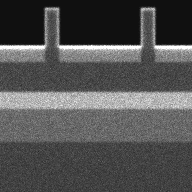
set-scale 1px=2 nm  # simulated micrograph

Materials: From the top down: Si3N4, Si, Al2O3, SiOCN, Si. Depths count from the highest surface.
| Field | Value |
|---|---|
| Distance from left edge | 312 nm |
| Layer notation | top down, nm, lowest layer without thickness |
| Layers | empty 76, Si3N4 32, Si 60, Al2O3 34, SiOCN 66, Si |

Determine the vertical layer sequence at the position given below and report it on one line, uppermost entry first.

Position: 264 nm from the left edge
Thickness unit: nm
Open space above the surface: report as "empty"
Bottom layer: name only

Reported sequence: empty 76, Si3N4 32, Si 60, Al2O3 34, SiOCN 66, Si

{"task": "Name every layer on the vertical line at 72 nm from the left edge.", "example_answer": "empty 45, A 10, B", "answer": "empty 76, Si3N4 32, Si 60, Al2O3 34, SiOCN 66, Si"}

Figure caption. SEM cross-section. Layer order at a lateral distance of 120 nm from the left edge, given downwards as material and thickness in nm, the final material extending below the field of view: empty 76, Si3N4 32, Si 60, Al2O3 34, SiOCN 66, Si